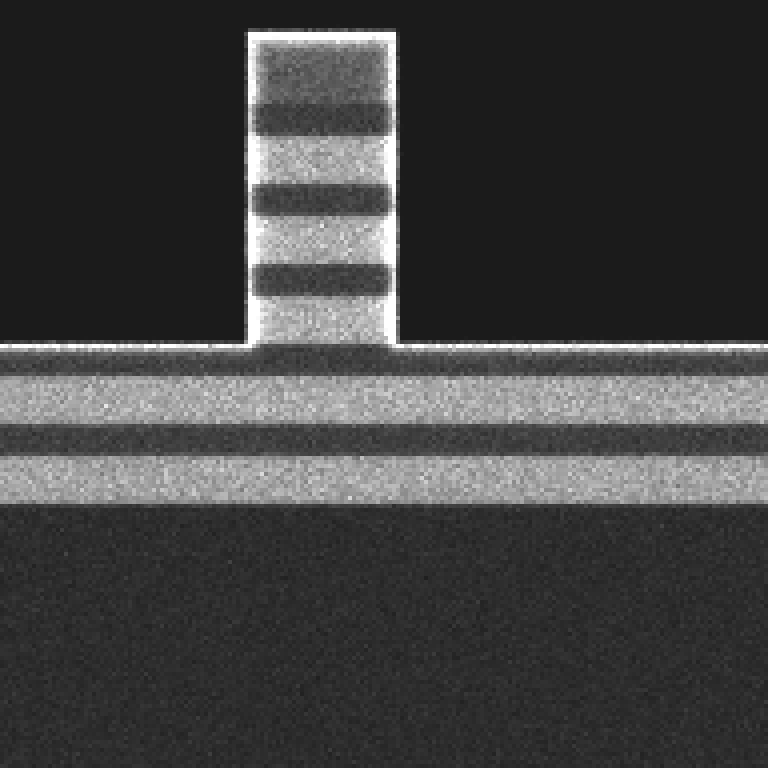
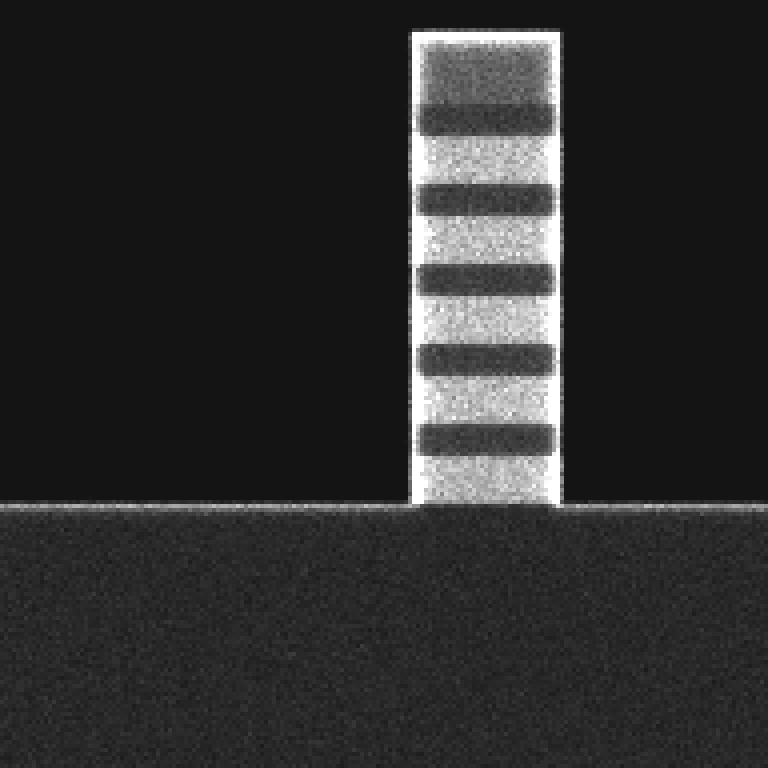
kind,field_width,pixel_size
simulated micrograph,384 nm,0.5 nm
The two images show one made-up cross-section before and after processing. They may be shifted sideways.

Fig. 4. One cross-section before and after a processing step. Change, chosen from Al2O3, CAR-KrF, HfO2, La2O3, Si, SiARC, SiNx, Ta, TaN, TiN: HfO2 and SiNx removed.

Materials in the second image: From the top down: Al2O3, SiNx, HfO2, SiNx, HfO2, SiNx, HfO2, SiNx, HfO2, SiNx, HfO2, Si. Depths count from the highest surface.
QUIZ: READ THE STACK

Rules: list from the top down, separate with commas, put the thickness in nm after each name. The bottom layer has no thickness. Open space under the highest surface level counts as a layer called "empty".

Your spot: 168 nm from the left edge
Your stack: empty 236, Si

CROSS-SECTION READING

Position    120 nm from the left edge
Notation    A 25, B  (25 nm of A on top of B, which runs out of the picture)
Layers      empty 236, Si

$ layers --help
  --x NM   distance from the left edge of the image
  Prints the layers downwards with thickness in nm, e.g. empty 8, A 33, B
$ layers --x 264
Al2O3 36, SiNx 16, HfO2 24, SiNx 16, HfO2 24, SiNx 16, HfO2 24, SiNx 16, HfO2 24, SiNx 16, HfO2 24, Si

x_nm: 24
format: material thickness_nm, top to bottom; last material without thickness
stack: empty 236, Si